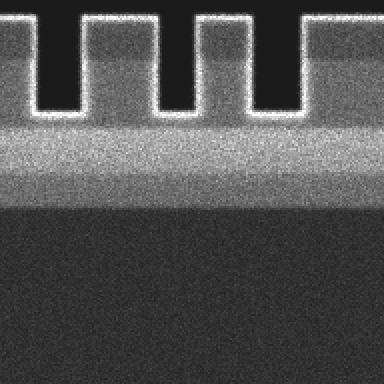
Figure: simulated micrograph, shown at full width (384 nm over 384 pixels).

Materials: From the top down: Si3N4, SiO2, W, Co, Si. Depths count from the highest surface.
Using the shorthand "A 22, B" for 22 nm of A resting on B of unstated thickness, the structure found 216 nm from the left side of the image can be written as Si3N4 44, SiO2 68, W 46, Co 34, Si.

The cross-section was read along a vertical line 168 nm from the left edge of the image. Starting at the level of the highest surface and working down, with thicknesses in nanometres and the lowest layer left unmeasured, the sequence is empty 96, SiO2 16, W 46, Co 34, Si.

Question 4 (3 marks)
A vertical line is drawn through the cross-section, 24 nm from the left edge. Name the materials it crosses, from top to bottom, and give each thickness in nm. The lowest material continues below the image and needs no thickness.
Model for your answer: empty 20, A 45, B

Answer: Si3N4 44, SiO2 68, W 46, Co 34, Si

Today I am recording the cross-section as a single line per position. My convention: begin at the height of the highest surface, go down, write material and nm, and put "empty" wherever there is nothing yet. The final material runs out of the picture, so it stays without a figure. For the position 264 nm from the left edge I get empty 96, SiO2 16, W 46, Co 34, Si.